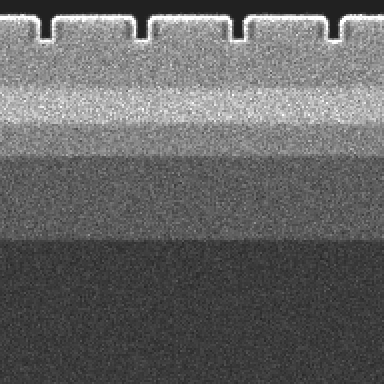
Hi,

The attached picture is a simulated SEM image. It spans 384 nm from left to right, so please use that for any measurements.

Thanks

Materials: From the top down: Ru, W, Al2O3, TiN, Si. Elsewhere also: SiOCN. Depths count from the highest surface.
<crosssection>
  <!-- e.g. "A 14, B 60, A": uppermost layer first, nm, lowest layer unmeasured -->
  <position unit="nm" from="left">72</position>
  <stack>Ru 72, W 36, Al2O3 32, TiN 84, Si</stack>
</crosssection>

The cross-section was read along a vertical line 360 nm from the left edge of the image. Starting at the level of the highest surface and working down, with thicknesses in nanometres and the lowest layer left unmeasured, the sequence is Ru 72, W 36, Al2O3 32, TiN 84, Si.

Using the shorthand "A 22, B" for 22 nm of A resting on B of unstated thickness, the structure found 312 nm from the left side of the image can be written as Ru 72, W 36, Al2O3 32, TiN 84, Si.